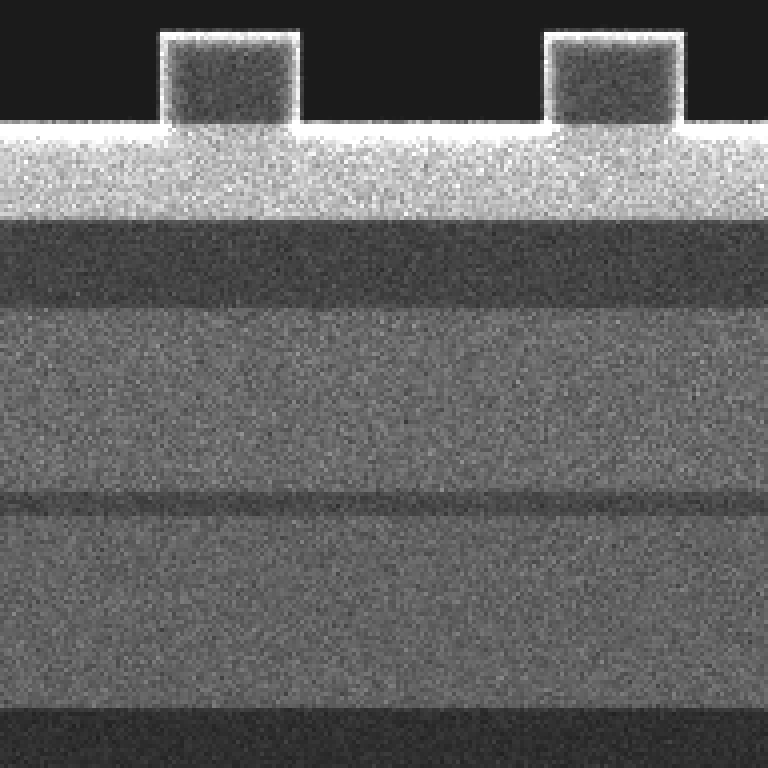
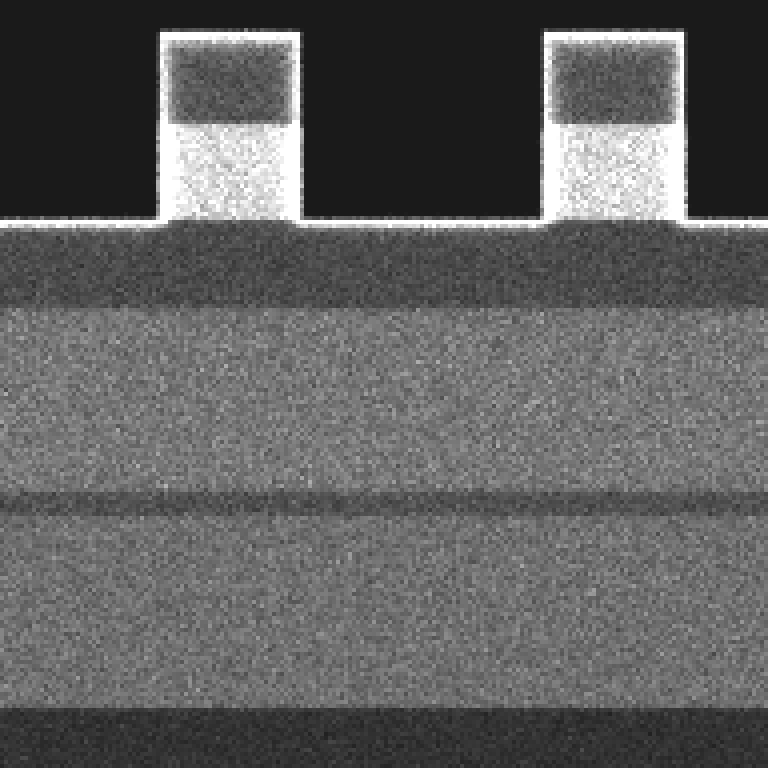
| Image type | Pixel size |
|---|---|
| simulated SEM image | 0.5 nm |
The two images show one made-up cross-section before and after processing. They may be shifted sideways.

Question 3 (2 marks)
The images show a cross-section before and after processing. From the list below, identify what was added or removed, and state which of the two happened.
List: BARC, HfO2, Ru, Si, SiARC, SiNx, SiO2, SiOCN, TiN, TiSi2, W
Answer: HfO2 was removed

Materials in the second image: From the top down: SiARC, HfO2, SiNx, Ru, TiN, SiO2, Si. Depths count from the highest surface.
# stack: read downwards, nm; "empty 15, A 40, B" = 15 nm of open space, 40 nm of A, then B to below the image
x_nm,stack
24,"empty 94, SiNx 44, Ru 92, TiN 12, SiO2 96, Si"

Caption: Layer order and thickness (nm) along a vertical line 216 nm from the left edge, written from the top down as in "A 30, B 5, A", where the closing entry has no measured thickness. empty 94, SiNx 44, Ru 92, TiN 12, SiO2 96, Si